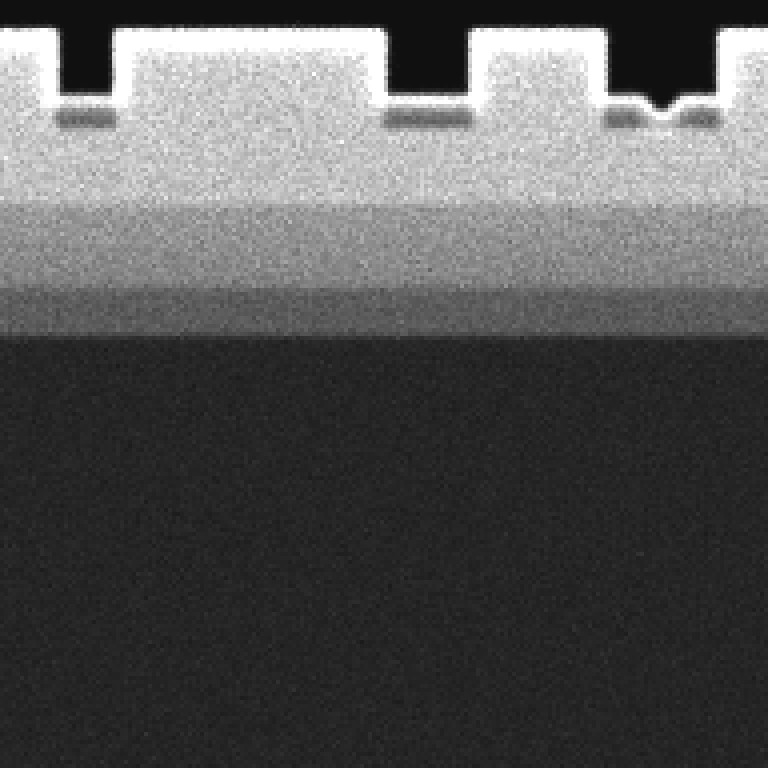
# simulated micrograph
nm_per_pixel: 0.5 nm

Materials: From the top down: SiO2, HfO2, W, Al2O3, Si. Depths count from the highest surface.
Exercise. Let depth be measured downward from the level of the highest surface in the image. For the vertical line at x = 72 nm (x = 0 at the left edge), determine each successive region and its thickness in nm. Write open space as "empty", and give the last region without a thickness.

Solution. HfO2 86, W 42, Al2O3 24, Si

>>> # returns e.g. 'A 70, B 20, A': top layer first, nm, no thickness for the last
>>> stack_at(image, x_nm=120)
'HfO2 86, W 42, Al2O3 24, Si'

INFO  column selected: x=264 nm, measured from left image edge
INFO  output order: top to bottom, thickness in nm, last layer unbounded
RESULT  HfO2 86, W 42, Al2O3 24, Si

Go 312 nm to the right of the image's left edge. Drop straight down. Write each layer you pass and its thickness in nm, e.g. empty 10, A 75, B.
empty 32, SiO2 16, HfO2 38, W 42, Al2O3 24, Si